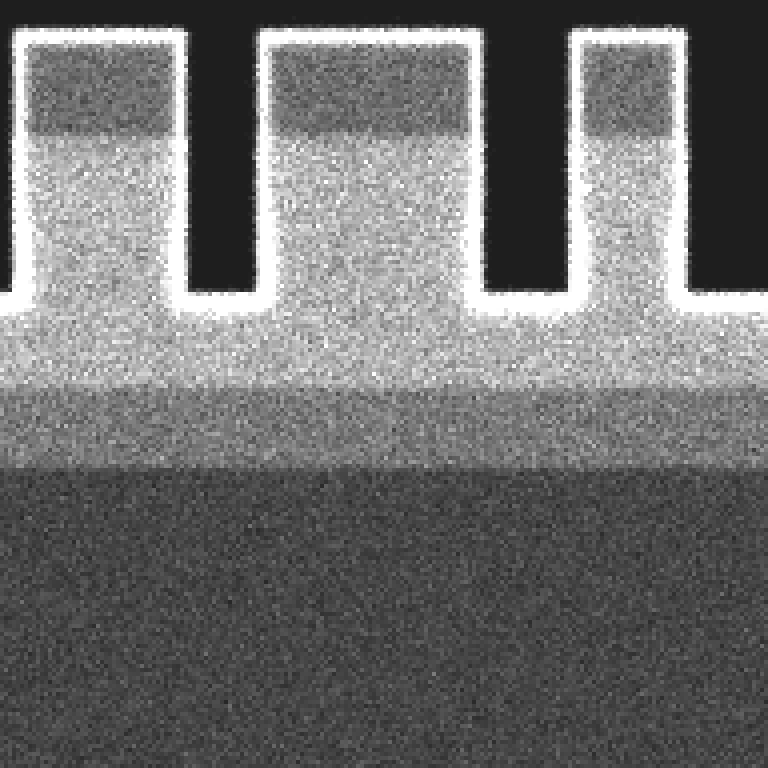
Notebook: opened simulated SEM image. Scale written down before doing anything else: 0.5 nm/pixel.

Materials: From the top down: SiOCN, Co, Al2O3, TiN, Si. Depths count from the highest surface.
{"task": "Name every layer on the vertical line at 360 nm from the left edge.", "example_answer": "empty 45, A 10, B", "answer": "empty 132, Al2O3 46, TiN 40, Si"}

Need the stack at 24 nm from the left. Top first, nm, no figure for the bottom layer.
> SiOCN 52, Co 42, Al2O3 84, TiN 40, Si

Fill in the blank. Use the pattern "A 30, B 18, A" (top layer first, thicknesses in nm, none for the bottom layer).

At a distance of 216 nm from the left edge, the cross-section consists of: SiOCN 52, Co 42, Al2O3 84, TiN 40, Si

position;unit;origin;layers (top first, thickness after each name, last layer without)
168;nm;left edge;SiOCN 52, Co 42, Al2O3 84, TiN 40, Si